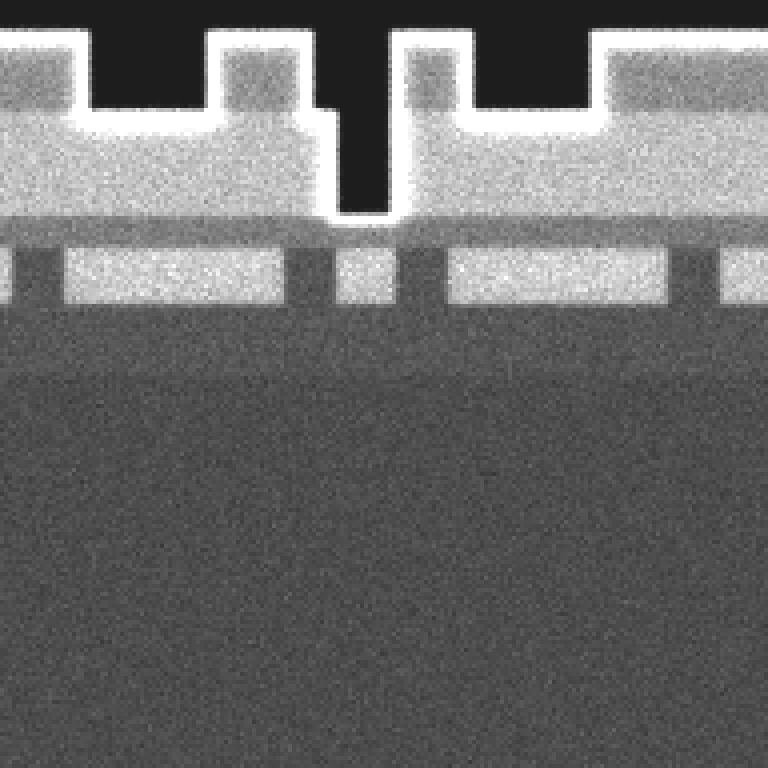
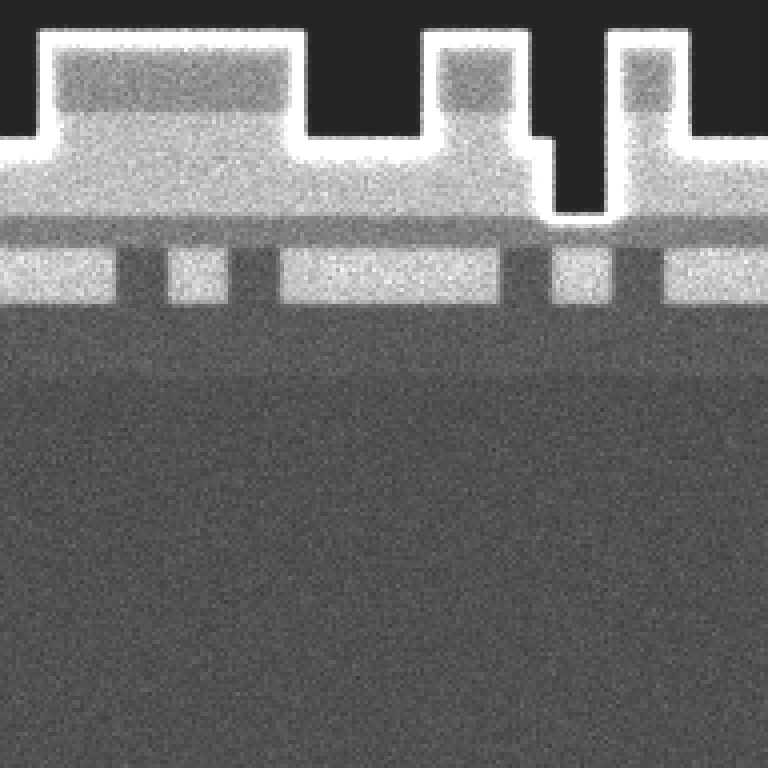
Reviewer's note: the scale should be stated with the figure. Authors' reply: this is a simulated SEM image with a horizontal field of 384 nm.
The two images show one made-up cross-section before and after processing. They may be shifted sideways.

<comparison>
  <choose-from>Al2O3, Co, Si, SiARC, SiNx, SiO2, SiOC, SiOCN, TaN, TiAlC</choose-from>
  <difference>SiO2 removed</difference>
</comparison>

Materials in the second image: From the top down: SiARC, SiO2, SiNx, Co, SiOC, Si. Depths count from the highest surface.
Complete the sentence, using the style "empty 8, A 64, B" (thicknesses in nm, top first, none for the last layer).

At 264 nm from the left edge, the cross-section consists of empty 54, SiO2 38, SiNx 16, SiOC 64, Si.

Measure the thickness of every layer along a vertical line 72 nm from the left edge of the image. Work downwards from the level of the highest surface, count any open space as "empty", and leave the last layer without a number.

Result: SiARC 40, SiO2 52, SiNx 16, SiOC 64, Si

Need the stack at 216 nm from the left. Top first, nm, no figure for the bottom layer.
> SiARC 40, SiO2 52, SiNx 16, Co 28, SiOC 36, Si